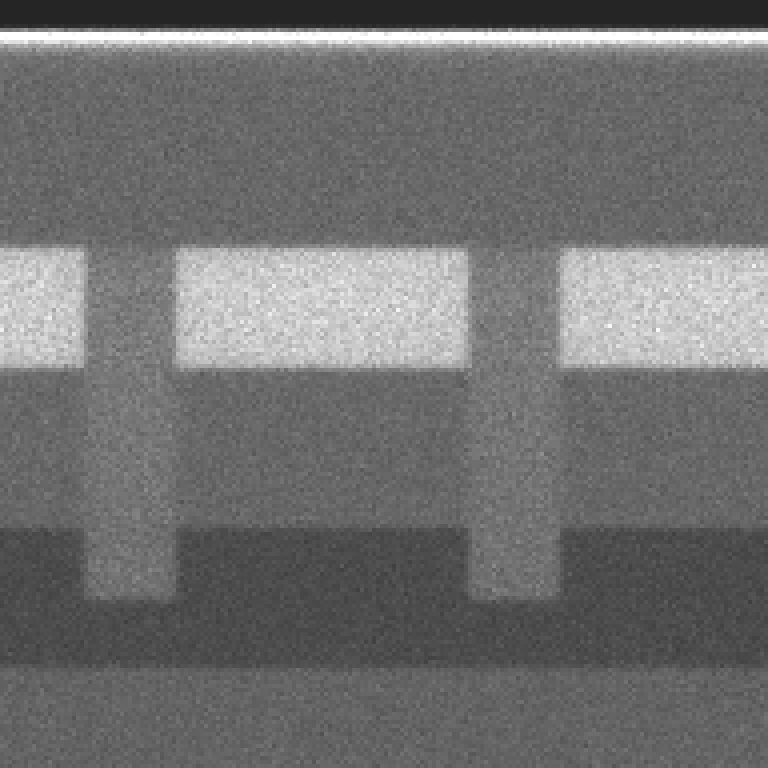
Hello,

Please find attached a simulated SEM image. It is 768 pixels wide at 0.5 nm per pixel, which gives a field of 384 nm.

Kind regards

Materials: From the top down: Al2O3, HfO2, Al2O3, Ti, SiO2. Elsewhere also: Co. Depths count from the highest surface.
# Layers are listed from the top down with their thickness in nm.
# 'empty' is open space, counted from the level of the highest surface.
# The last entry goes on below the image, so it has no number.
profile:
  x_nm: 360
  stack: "Al2O3 108, HfO2 60, Al2O3 80, Ti 70, SiO2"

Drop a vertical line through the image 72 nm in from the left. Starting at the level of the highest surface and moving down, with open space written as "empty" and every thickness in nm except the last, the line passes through Al2O3 108, Co 176, Ti 34, SiO2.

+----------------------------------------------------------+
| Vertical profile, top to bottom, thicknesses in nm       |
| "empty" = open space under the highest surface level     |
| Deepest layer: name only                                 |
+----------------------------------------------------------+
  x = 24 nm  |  Al2O3 108, HfO2 60, Al2O3 80, Ti 70, SiO2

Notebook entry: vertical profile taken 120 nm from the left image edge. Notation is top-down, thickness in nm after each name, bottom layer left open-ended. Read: Al2O3 108, HfO2 60, Al2O3 80, Ti 70, SiO2